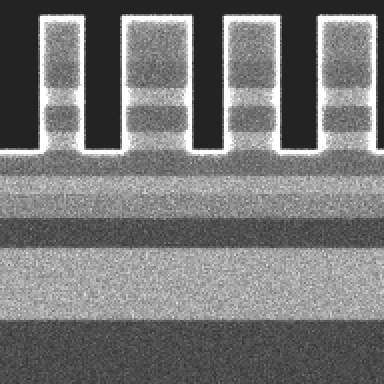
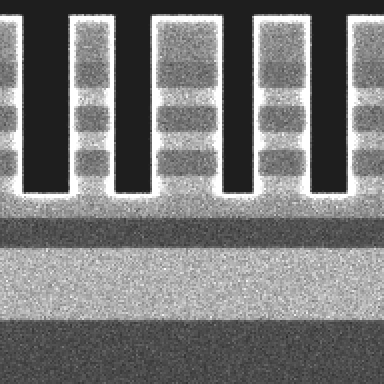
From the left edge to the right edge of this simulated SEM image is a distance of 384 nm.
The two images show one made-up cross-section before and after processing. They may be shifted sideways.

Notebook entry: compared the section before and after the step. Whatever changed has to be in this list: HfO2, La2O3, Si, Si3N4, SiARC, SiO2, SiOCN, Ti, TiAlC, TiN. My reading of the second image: SiO2 and SiOCN removed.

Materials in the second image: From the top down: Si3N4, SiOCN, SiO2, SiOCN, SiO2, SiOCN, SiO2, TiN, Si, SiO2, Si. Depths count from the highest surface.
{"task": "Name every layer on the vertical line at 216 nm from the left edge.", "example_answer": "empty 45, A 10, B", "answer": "Si3N4 46, SiOCN 26, SiO2 18, SiOCN 26, SiO2 18, SiOCN 26, SiO2 18, TiN 24, Si 30, SiO2 72, Si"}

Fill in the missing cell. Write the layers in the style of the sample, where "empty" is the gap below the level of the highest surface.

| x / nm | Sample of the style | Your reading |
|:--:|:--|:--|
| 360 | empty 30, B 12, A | Si3N4 46, SiOCN 26, SiO2 18, SiOCN 26, SiO2 18, SiOCN 26, SiO2 18, TiN 24, Si 30, SiO2 72, Si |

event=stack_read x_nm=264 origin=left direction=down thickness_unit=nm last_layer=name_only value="Si3N4 46, SiOCN 26, SiO2 18, SiOCN 26, SiO2 18, SiOCN 26, SiO2 18, TiN 24, Si 30, SiO2 72, Si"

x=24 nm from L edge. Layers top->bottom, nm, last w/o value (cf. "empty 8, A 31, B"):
empty 178, TiN 24, Si 30, SiO2 72, Si